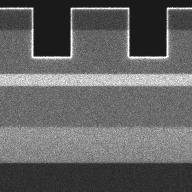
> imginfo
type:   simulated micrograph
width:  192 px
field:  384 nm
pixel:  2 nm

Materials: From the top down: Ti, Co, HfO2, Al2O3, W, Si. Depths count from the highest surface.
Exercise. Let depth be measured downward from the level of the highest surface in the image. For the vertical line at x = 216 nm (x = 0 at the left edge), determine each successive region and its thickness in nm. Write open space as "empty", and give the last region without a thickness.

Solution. Ti 44, Co 88, HfO2 24, Al2O3 82, W 72, Si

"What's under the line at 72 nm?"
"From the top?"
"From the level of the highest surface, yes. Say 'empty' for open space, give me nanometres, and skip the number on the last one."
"empty 98, Co 34, HfO2 24, Al2O3 82, W 72, Si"